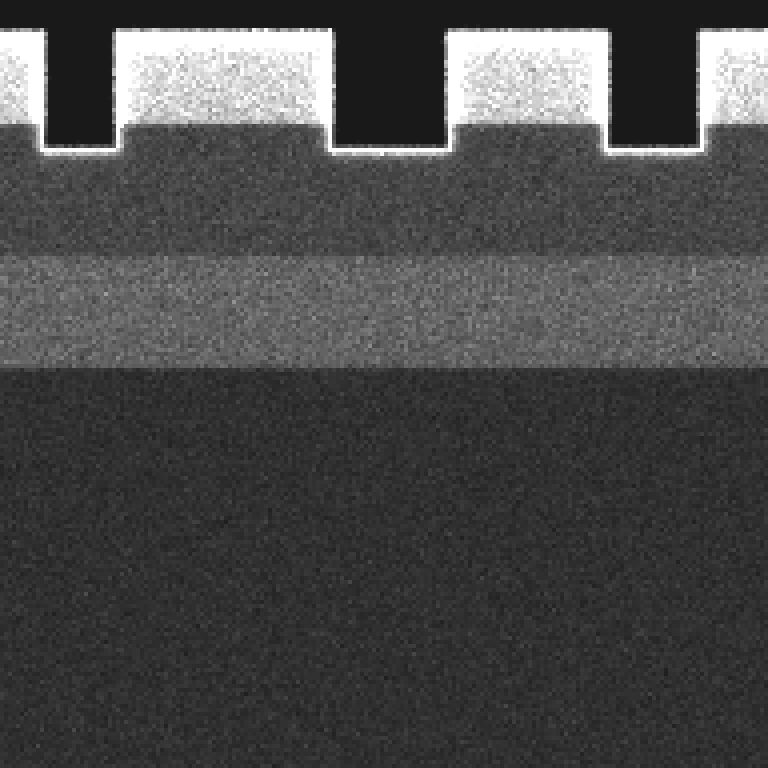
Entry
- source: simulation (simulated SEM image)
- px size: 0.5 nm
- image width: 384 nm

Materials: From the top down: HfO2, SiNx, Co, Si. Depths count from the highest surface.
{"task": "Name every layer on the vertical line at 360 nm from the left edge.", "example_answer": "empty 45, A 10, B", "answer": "HfO2 46, SiNx 66, Co 56, Si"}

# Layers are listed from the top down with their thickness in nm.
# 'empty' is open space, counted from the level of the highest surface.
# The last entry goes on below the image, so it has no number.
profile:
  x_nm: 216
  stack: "empty 58, SiNx 54, Co 56, Si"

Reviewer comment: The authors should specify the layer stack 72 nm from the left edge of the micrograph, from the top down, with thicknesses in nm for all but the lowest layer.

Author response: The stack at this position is HfO2 46, SiNx 66, Co 56, Si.